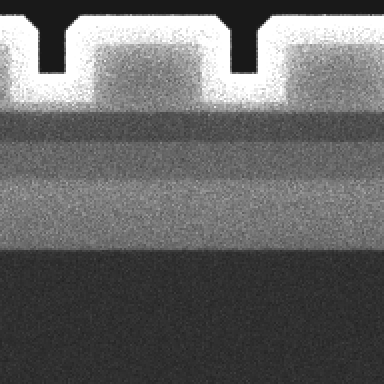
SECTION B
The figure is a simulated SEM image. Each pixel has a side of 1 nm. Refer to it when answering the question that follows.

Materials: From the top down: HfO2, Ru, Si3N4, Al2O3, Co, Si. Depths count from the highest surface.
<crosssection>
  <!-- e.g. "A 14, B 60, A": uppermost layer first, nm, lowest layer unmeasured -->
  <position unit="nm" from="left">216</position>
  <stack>empty 2, HfO2 84, Ru 10, Si3N4 30, Al2O3 38, Co 70, Si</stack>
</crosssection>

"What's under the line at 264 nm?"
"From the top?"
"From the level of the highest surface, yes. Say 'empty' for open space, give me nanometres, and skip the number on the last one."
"empty 8, HfO2 78, Ru 10, Si3N4 30, Al2O3 38, Co 70, Si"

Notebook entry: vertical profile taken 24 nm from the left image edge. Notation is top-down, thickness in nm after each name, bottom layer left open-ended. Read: empty 2, HfO2 84, Ru 10, Si3N4 30, Al2O3 38, Co 70, Si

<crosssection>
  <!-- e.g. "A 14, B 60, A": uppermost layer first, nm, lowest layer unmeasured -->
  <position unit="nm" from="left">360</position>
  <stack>HfO2 28, Ru 68, Si3N4 30, Al2O3 38, Co 70, Si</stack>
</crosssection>